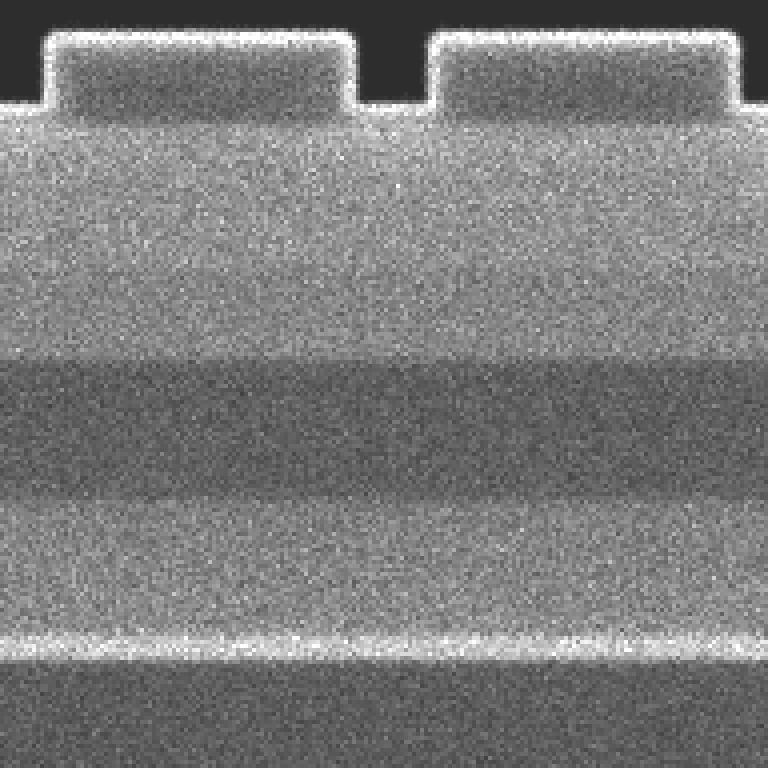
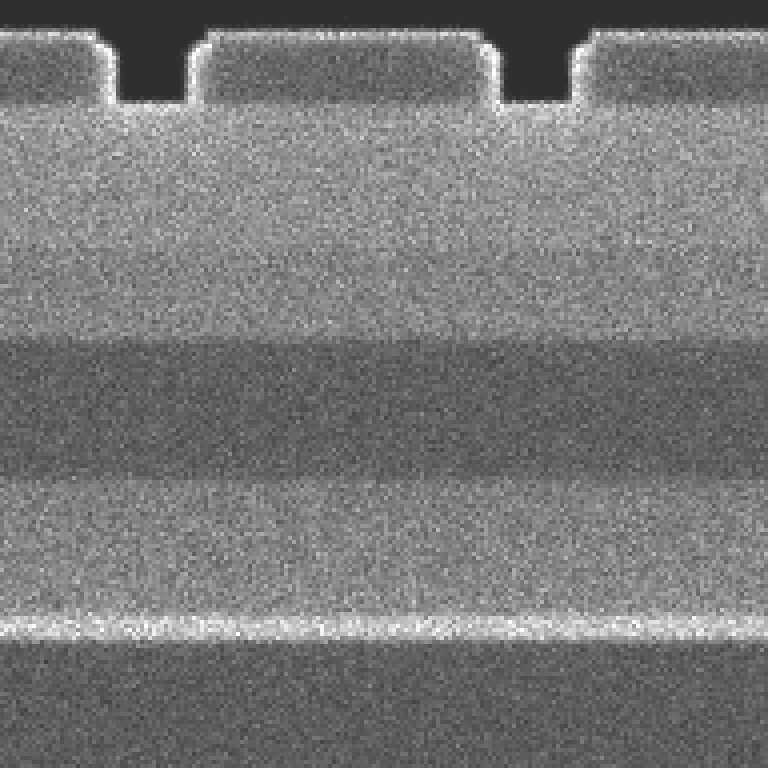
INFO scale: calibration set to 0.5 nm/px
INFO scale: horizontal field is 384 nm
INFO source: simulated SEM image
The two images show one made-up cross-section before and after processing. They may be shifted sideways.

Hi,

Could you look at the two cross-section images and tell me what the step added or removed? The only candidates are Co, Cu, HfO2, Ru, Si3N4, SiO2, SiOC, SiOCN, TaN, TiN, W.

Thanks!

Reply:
removed SiO2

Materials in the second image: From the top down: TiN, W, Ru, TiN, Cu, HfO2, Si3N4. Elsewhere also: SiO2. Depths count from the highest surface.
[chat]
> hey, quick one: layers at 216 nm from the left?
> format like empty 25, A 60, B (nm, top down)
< TiN 36, W 72, Ru 46, TiN 70, Cu 68, HfO2 12, Si3N4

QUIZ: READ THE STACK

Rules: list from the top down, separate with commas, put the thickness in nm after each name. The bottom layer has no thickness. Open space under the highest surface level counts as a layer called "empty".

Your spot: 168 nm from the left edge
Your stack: TiN 36, W 72, Ru 46, TiN 70, Cu 68, HfO2 12, Si3N4